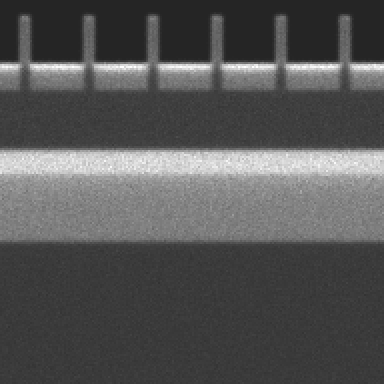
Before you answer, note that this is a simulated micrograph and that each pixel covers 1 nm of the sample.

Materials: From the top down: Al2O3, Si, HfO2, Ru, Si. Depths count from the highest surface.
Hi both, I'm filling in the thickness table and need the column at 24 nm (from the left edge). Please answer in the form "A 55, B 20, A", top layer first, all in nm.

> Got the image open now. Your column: Si 134, HfO2 24, Ru 68, Si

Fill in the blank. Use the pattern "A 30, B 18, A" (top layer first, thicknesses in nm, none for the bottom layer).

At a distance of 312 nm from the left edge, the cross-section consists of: empty 48, Al2O3 26, Si 60, HfO2 24, Ru 68, Si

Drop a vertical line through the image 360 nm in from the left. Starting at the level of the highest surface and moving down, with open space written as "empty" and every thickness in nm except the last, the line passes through empty 48, Al2O3 26, Si 60, HfO2 24, Ru 68, Si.